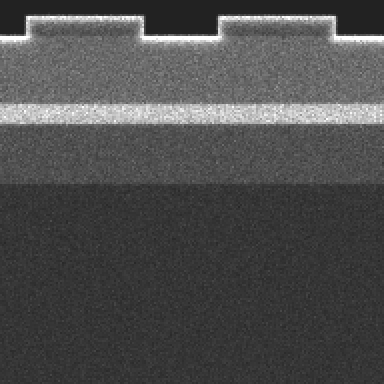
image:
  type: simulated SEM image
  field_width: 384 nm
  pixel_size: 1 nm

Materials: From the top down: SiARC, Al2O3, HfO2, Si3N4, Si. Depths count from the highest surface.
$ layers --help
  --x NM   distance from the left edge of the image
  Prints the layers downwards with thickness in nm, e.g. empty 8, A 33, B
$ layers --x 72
SiARC 20, Al2O3 68, HfO2 20, Si3N4 60, Si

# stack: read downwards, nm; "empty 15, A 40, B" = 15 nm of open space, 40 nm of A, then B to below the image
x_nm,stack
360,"empty 20, Al2O3 68, HfO2 20, Si3N4 60, Si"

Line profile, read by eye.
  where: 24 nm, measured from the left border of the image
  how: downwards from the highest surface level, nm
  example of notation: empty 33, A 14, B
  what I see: empty 20, Al2O3 68, HfO2 20, Si3N4 60, Si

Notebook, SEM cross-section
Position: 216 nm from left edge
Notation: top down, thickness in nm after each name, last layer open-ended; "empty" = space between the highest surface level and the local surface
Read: empty 20, Al2O3 68, HfO2 20, Si3N4 60, Si